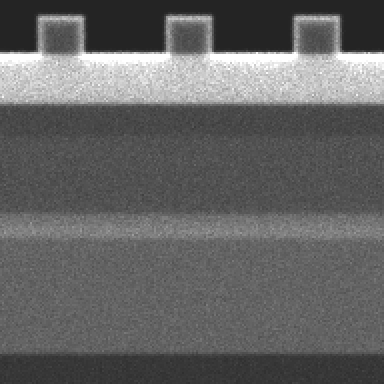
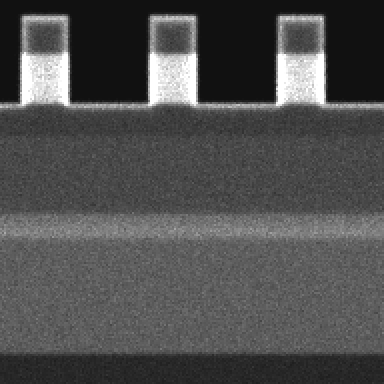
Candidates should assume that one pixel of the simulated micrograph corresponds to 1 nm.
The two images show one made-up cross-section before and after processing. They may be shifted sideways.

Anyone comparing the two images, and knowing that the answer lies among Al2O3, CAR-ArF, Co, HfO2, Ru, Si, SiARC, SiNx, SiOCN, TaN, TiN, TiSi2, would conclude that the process removed HfO2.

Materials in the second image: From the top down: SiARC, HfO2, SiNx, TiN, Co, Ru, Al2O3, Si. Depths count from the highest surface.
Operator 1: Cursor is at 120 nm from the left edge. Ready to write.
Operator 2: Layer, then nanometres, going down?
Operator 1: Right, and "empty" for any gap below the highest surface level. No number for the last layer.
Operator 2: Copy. empty 88, SiNx 32, TiN 78, Co 12, Ru 12, Al2O3 116, Si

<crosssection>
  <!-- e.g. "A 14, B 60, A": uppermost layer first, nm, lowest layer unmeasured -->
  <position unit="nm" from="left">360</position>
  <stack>empty 88, SiNx 32, TiN 78, Co 12, Ru 12, Al2O3 116, Si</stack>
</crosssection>